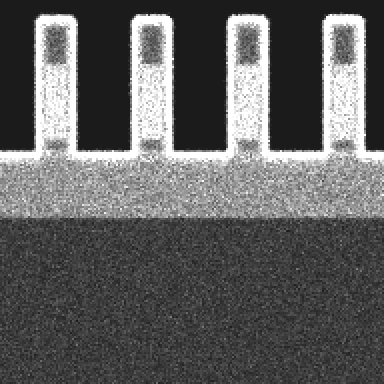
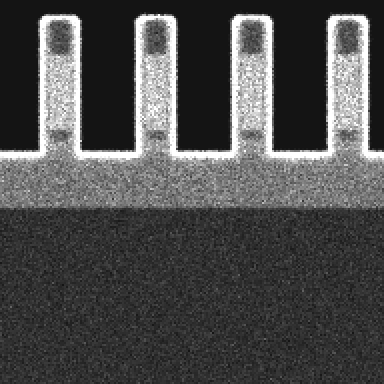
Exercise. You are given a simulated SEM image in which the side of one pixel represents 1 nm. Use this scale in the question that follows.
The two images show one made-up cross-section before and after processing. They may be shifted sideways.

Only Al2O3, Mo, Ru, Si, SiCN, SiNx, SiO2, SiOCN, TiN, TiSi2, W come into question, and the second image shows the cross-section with SiO2 removed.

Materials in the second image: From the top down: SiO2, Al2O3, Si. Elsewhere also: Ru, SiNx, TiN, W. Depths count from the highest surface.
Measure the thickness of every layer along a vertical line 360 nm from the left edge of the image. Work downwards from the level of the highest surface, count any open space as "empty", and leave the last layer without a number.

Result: SiO2 136, Al2O3 56, Si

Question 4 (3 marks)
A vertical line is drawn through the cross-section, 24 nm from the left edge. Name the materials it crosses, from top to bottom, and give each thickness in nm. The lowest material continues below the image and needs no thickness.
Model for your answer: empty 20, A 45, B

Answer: empty 136, Al2O3 56, Si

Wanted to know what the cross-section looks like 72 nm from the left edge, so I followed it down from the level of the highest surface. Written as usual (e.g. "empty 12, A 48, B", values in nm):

SiO2 136, Al2O3 56, Si